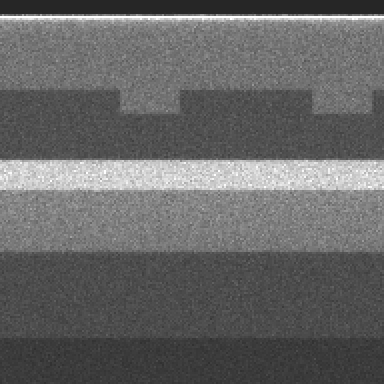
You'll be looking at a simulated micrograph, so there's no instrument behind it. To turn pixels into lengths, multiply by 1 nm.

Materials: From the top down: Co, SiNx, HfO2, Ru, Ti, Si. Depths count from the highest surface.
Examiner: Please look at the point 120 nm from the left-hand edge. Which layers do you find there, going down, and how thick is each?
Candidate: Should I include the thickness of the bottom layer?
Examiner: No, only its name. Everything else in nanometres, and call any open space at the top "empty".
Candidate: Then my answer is Co 98, SiNx 46, HfO2 30, Ru 62, Ti 86, Si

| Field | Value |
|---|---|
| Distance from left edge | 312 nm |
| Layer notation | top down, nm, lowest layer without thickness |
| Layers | Co 98, SiNx 46, HfO2 30, Ru 62, Ti 86, Si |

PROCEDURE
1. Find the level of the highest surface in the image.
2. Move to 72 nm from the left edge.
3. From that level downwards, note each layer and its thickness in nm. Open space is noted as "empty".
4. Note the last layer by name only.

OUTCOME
Co 74, SiNx 70, HfO2 30, Ru 62, Ti 86, Si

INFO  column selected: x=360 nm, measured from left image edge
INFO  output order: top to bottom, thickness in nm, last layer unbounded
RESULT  Co 98, SiNx 46, HfO2 30, Ru 62, Ti 86, Si